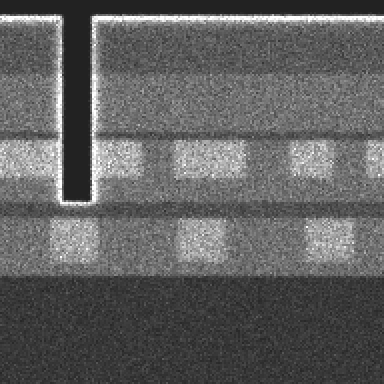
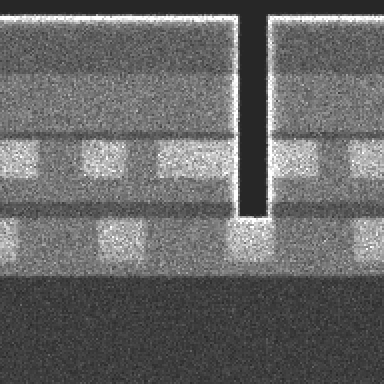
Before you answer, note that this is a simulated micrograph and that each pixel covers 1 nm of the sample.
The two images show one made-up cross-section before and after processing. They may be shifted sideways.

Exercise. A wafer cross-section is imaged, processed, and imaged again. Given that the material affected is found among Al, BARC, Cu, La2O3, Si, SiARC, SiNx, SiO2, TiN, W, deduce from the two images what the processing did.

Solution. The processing removed SiNx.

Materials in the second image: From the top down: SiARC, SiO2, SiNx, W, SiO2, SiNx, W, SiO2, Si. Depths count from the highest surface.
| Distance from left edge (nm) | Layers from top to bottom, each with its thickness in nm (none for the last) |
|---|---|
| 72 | SiARC 58, SiO2 58, SiNx 8, SiO2 62, SiNx 16, SiO2 58, Si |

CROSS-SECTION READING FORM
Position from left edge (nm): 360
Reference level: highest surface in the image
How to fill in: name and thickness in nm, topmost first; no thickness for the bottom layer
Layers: SiARC 58, SiO2 58, SiNx 8, W 38, SiO2 24, SiNx 16, W 44, SiO2 14, Si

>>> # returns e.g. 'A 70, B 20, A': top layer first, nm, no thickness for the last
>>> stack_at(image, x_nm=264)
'empty 202, W 44, SiO2 14, Si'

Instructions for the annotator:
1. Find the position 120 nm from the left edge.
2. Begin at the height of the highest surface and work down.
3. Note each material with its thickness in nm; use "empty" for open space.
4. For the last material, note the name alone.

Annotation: SiARC 58, SiO2 58, SiNx 8, W 38, SiO2 24, SiNx 16, W 44, SiO2 14, Si